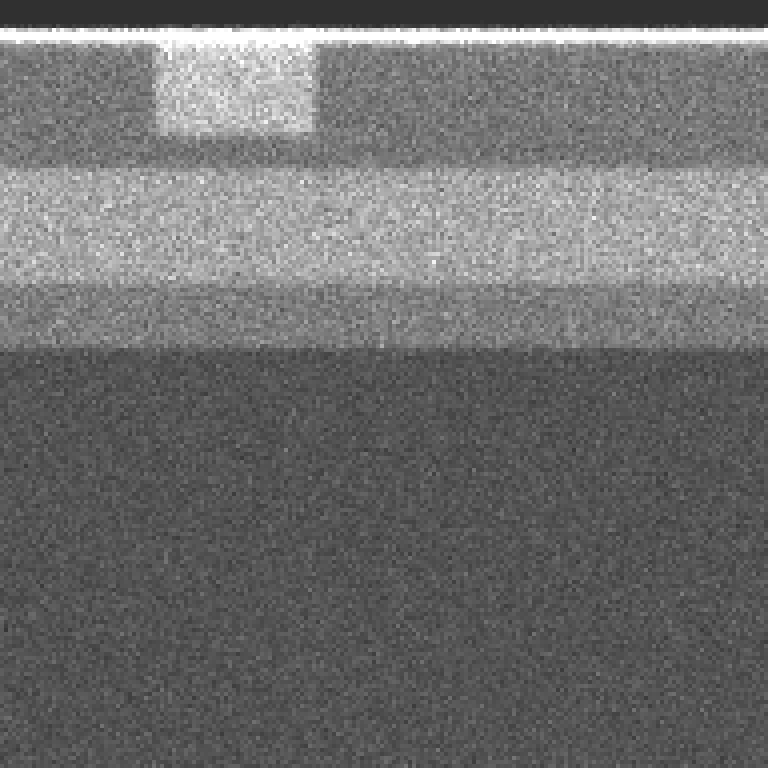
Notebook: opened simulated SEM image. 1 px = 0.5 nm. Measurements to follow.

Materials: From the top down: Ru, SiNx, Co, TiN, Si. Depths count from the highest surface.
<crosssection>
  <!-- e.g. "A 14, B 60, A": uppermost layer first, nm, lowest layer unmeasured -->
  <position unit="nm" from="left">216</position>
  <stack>SiNx 68, Co 58, TiN 32, Si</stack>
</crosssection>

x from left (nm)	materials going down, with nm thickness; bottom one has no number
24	SiNx 68, Co 58, TiN 32, Si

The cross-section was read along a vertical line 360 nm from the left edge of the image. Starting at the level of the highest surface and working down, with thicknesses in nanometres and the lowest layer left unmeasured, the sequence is SiNx 68, Co 58, TiN 32, Si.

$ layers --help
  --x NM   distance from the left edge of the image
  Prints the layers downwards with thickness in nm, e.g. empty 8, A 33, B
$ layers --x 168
SiNx 68, Co 58, TiN 32, Si